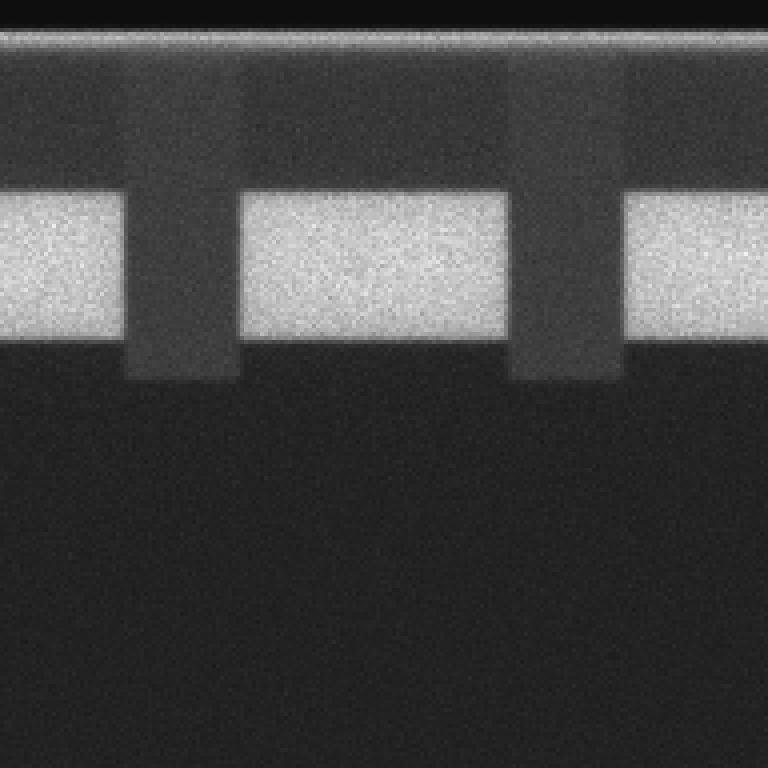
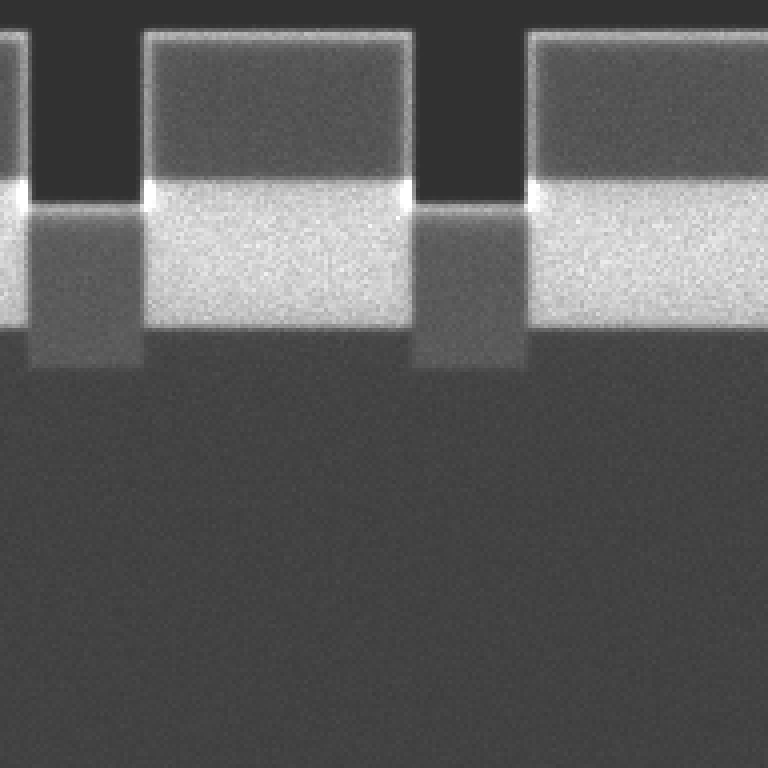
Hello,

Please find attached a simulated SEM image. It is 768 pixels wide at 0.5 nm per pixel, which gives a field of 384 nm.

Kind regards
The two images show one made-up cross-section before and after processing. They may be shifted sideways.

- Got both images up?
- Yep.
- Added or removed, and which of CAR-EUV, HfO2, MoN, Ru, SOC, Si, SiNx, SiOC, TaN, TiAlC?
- removed, SOC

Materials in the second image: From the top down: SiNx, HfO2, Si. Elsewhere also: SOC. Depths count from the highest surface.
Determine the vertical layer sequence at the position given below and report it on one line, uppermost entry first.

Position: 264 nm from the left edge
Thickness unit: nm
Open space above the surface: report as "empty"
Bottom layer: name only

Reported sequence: SiNx 74, HfO2 74, Si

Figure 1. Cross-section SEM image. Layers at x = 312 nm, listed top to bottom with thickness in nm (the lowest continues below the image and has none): SiNx 74, HfO2 74, Si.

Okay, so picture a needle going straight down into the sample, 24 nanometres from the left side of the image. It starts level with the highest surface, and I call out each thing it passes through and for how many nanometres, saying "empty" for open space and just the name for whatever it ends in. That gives empty 86, SOC 82, Si